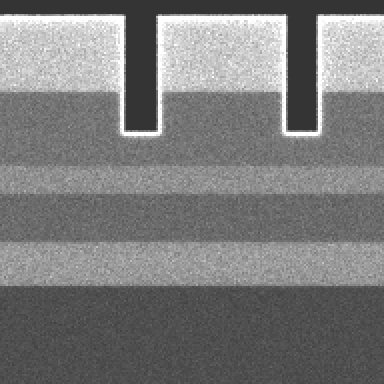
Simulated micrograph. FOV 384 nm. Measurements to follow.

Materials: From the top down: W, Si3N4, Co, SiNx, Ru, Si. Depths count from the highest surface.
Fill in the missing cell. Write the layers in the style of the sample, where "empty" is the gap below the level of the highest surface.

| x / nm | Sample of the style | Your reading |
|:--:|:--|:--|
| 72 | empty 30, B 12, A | W 76, Si3N4 74, Co 28, SiNx 48, Ru 44, Si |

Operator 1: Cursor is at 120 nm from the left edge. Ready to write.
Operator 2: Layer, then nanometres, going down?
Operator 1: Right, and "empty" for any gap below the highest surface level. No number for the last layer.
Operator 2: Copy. W 76, Si3N4 74, Co 28, SiNx 48, Ru 44, Si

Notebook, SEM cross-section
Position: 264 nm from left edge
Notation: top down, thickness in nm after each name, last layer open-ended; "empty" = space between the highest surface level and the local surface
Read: W 76, Si3N4 74, Co 28, SiNx 48, Ru 44, Si